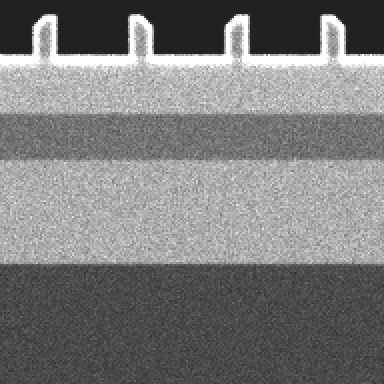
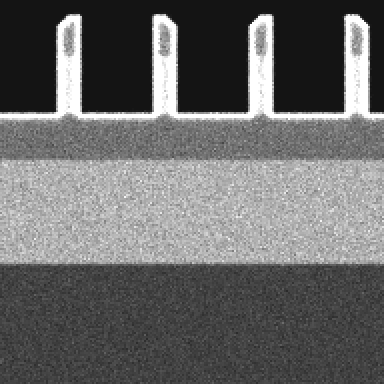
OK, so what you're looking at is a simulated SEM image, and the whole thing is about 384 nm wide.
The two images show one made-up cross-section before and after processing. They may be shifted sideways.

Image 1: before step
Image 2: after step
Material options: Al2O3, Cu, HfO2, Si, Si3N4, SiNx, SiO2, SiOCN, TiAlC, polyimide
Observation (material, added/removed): Al2O3, removed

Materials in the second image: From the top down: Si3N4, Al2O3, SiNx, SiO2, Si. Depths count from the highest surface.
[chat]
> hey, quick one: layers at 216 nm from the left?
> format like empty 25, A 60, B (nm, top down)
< empty 98, SiNx 46, SiO2 104, Si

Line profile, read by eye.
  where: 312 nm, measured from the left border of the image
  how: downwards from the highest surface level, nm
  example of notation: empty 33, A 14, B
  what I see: empty 98, SiNx 46, SiO2 104, Si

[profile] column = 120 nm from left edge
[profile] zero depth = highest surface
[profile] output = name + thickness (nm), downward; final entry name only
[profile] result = empty 98, SiNx 46, SiO2 104, Si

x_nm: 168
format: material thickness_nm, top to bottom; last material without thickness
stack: empty 4, Si3N4 36, Al2O3 58, SiNx 46, SiO2 104, Si